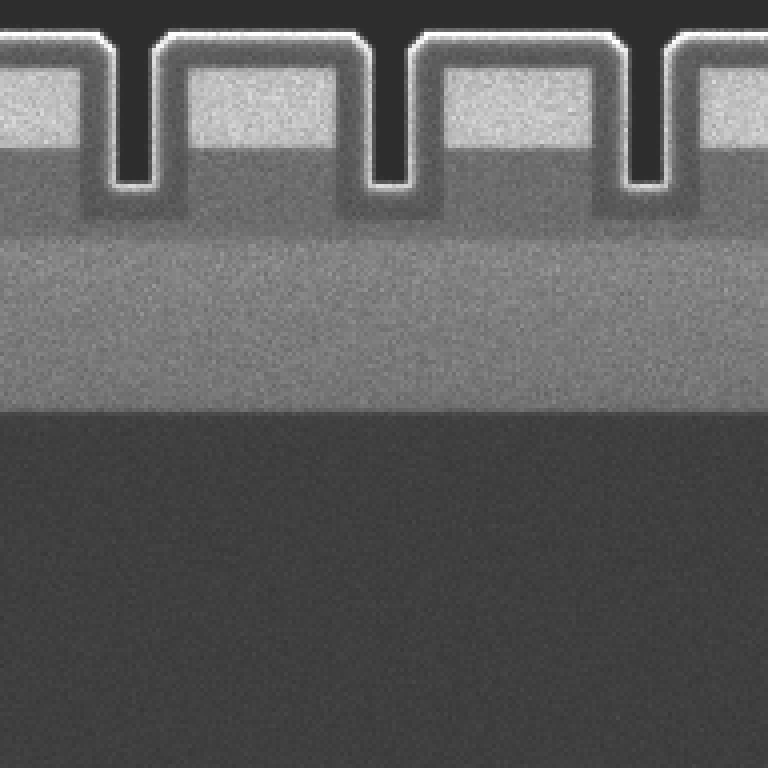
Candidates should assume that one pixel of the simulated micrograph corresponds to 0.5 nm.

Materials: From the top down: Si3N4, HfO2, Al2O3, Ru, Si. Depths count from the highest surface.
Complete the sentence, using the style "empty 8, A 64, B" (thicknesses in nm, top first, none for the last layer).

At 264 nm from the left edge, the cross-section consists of Si3N4 18, HfO2 40, Al2O3 46, Ru 86, Si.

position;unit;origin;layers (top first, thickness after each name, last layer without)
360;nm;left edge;Si3N4 18, HfO2 40, Al2O3 46, Ru 86, Si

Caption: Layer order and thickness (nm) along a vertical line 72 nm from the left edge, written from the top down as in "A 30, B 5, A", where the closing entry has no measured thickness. empty 76, Si3N4 18, Al2O3 10, Ru 86, Si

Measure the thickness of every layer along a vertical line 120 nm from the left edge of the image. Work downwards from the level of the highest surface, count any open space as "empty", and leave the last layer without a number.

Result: Si3N4 18, HfO2 40, Al2O3 46, Ru 86, Si